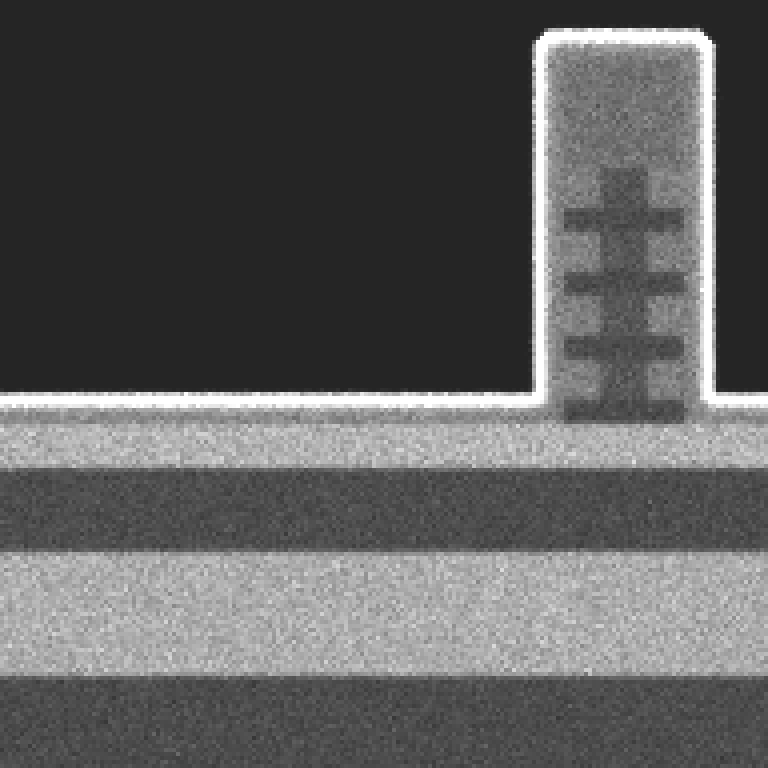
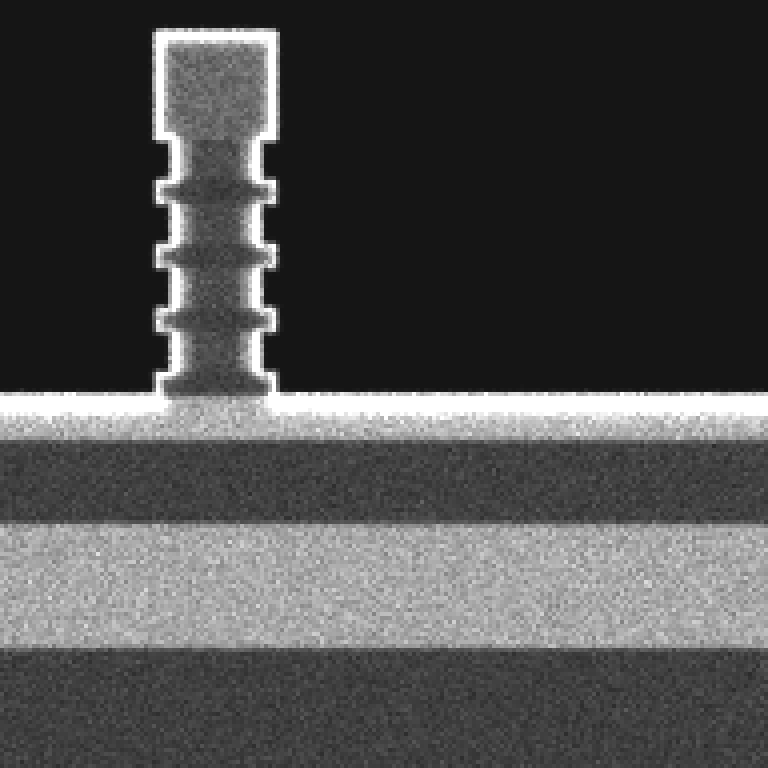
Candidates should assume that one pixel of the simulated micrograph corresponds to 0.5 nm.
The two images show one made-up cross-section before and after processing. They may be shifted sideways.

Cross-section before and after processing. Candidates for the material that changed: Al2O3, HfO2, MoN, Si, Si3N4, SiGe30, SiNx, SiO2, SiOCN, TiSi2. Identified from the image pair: Si3N4 (removed).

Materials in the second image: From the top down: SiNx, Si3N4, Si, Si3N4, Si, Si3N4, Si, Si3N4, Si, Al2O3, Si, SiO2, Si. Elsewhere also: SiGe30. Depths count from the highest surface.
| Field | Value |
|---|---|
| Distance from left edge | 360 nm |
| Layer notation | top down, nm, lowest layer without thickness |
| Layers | empty 182, Al2O3 22, Si 42, SiO2 62, Si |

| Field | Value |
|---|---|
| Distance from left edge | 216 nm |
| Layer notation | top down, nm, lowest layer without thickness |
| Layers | empty 182, Al2O3 22, Si 42, SiO2 62, Si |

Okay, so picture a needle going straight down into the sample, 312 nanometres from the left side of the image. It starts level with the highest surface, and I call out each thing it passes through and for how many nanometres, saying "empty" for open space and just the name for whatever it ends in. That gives empty 182, Al2O3 22, Si 42, SiO2 62, Si